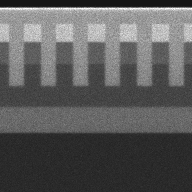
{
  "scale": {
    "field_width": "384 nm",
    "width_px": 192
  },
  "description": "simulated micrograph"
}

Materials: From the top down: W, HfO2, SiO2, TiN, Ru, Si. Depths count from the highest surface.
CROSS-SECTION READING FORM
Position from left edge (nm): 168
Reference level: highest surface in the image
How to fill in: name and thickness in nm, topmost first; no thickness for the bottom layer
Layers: W 156, TiN 42, Ru 52, Si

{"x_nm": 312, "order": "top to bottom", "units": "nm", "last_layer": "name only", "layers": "W 32, HfO2 36, SiO2 44, TiN 86, Ru 52, Si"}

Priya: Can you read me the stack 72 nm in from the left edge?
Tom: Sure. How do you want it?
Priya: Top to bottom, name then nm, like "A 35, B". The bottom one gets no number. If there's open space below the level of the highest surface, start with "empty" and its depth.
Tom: W 32, HfO2 36, SiO2 44, TiN 86, Ru 52, Si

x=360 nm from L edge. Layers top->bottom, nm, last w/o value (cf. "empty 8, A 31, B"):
W 156, TiN 42, Ru 52, Si